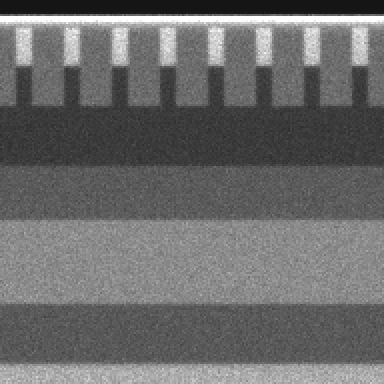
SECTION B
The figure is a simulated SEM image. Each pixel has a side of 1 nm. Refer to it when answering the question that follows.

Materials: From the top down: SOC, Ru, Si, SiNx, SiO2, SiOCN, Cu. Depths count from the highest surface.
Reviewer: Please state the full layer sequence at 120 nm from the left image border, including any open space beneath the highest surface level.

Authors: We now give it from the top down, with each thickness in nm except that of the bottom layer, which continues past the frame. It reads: SOC 12, Ru 38, Si 100, SiNx 54, SiO2 84, SiOCN 60, Cu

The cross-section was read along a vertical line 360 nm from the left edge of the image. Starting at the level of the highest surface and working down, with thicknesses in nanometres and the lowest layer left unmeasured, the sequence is SOC 12, Ru 38, Si 100, SiNx 54, SiO2 84, SiOCN 60, Cu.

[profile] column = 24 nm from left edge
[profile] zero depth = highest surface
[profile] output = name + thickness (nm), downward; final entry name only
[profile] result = SOC 12, Ru 38, Si 100, SiNx 54, SiO2 84, SiOCN 60, Cu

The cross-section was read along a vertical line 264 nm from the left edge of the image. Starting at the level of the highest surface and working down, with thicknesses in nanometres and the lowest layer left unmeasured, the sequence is SOC 12, Ru 38, Si 100, SiNx 54, SiO2 84, SiOCN 60, Cu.